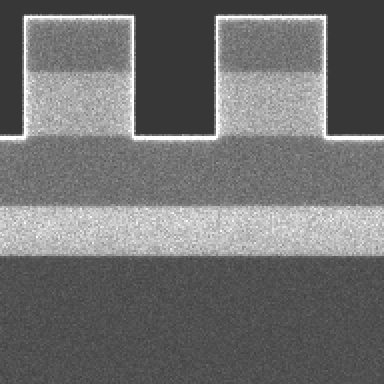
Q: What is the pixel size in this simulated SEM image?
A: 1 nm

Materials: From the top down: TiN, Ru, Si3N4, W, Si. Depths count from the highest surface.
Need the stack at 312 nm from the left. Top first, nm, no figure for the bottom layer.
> TiN 56, Ru 64, Si3N4 70, W 50, Si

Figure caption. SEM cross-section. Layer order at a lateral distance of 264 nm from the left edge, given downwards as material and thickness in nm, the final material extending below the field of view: TiN 56, Ru 64, Si3N4 70, W 50, Si